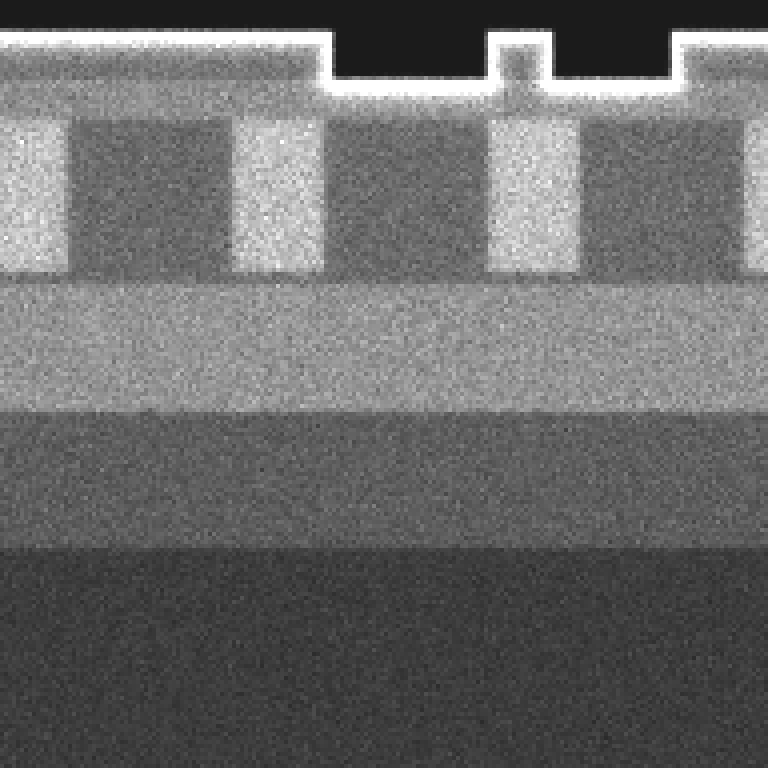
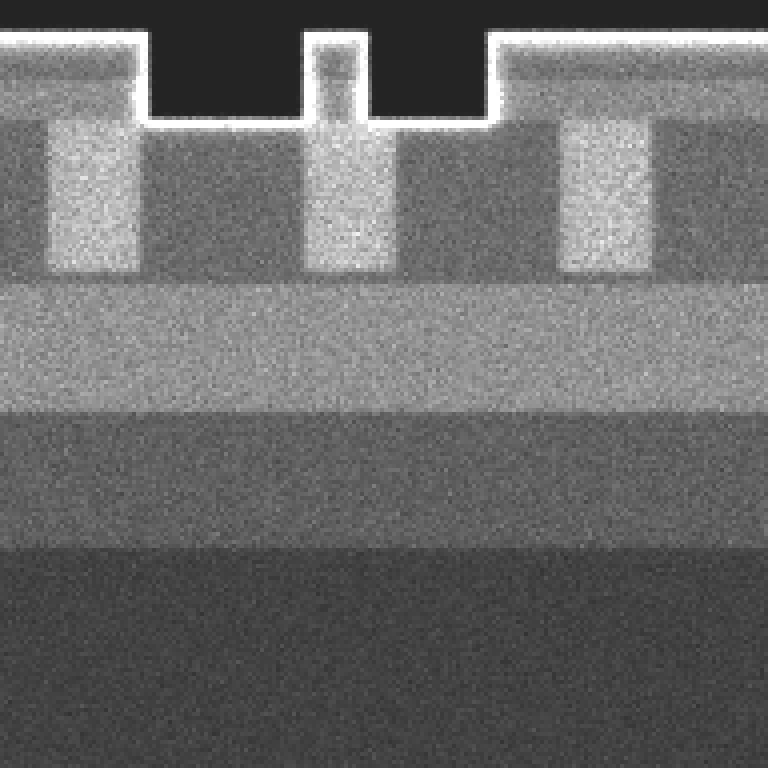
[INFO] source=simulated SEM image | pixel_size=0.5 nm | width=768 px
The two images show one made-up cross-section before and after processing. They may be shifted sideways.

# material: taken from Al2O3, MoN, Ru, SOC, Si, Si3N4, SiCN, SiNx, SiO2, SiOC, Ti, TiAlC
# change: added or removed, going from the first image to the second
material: SiO2
change: removed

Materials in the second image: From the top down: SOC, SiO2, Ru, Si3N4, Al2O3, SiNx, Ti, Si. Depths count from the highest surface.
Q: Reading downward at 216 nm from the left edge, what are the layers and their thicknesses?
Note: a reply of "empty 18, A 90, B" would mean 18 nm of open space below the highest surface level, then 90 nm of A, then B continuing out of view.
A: empty 44, Si3N4 82, Al2O3 64, SiNx 40, Ti 28, Si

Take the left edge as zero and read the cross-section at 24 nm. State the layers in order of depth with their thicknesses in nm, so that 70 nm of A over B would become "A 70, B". SOC 24, SiO2 20, Ru 76, Si3N4 6, Al2O3 64, SiNx 40, Ti 28, Si